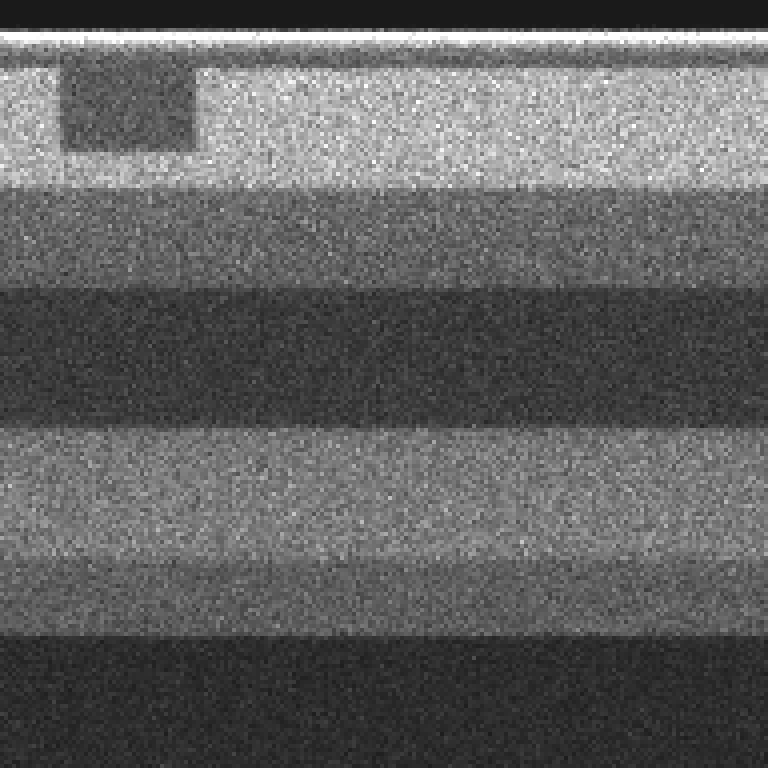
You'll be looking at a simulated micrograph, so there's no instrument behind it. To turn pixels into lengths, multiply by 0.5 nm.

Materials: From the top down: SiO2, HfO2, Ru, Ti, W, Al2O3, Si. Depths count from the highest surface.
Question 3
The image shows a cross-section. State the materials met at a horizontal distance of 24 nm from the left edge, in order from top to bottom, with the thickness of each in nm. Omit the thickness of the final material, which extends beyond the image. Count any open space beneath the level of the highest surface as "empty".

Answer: SiO2 18, HfO2 60, Ru 50, Ti 70, W 66, Al2O3 38, Si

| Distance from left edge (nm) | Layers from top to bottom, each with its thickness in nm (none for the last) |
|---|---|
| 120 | SiO2 18, HfO2 60, Ru 50, Ti 70, W 66, Al2O3 38, Si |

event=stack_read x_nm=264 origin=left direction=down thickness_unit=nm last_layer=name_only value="SiO2 18, HfO2 60, Ru 50, Ti 70, W 66, Al2O3 38, Si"